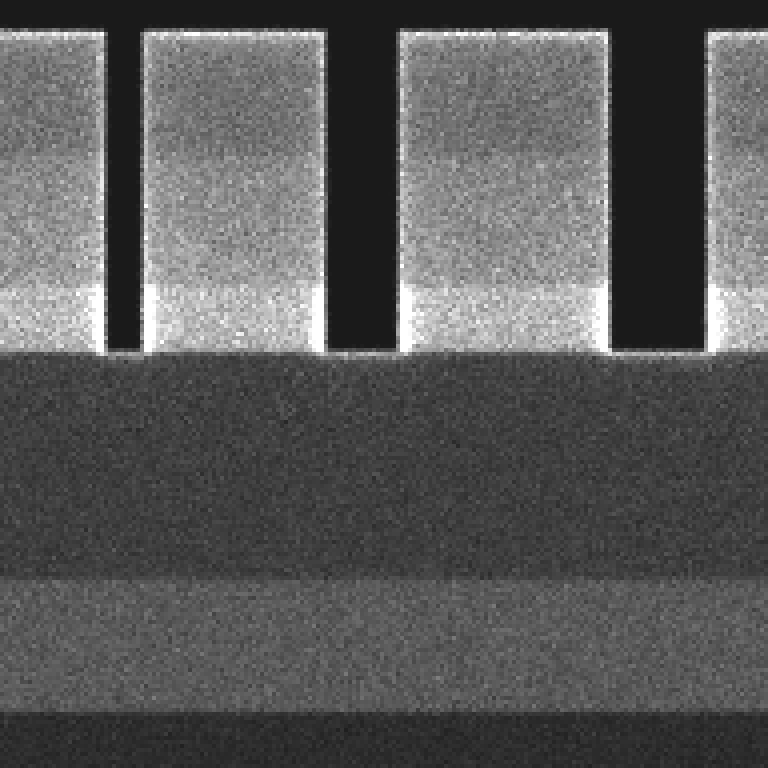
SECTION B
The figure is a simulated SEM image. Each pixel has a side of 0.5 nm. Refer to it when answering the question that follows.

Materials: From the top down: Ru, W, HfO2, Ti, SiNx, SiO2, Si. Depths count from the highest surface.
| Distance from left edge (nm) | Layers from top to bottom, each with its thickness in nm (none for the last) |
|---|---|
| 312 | empty 160, Ti 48, SiNx 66, SiO2 66, Si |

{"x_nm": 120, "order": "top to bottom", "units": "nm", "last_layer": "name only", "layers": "Ru 62, W 66, HfO2 32, Ti 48, SiNx 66, SiO2 66, Si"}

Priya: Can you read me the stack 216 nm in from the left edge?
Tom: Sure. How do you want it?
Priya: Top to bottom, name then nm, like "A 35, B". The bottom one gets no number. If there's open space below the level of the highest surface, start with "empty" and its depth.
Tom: Ru 62, W 66, HfO2 32, Ti 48, SiNx 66, SiO2 66, Si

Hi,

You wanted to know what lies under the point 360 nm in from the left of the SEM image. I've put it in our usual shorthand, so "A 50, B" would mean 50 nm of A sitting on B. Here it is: Ru 62, W 66, HfO2 32, Ti 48, SiNx 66, SiO2 66, Si